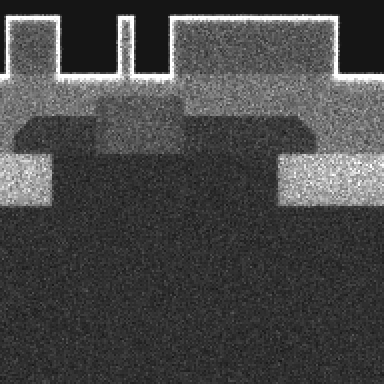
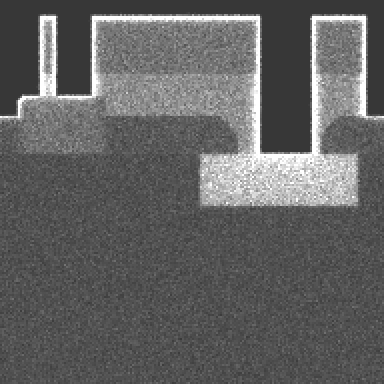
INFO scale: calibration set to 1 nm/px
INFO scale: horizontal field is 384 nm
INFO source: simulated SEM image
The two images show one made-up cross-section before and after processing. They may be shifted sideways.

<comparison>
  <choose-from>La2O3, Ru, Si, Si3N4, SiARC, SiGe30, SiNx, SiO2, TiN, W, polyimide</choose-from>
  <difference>SiO2 removed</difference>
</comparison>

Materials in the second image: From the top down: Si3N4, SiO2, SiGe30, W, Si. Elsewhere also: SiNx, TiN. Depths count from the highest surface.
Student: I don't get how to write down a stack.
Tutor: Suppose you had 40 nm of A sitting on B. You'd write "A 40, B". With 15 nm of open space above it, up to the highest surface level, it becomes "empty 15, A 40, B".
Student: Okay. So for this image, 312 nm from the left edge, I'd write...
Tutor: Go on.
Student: Si3N4 58, SiO2 80, W 52, Si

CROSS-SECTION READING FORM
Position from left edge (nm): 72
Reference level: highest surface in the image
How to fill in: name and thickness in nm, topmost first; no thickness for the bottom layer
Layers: empty 80, TiN 58, Si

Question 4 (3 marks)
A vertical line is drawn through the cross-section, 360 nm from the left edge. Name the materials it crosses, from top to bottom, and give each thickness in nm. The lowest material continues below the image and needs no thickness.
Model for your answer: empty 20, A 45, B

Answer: Si3N4 58, SiO2 42, SiGe30 38, Si